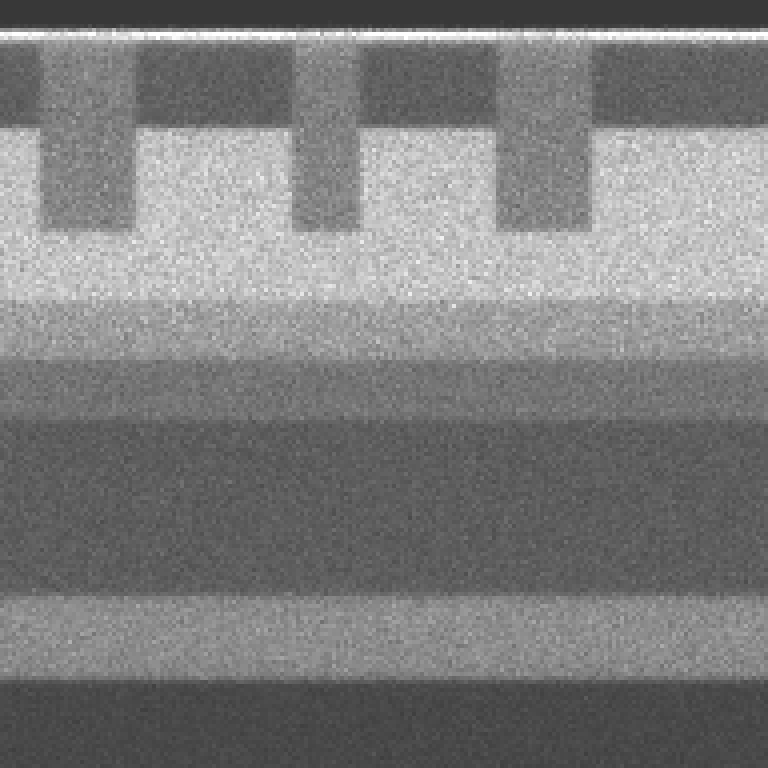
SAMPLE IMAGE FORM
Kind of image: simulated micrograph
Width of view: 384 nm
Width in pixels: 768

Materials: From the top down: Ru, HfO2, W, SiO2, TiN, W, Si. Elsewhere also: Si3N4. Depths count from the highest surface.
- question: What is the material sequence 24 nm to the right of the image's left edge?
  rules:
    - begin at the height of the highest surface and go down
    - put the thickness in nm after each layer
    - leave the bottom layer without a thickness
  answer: Ru 100, HfO2 34, W 30, SiO2 30, TiN 88, W 42, Si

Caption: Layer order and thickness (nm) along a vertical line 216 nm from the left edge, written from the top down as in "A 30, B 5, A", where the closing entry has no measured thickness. Si3N4 48, HfO2 86, W 30, SiO2 30, TiN 88, W 42, Si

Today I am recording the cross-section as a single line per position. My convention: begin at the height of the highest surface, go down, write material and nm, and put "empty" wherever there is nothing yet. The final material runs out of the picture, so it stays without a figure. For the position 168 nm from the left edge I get Ru 100, HfO2 34, W 30, SiO2 30, TiN 88, W 42, Si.